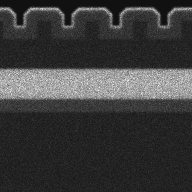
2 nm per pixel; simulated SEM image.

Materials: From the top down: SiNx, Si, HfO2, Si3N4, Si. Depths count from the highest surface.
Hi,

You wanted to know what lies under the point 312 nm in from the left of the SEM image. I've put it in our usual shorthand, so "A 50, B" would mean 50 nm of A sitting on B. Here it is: empty 6, SiNx 56, Si 60, HfO2 60, Si3N4 26, Si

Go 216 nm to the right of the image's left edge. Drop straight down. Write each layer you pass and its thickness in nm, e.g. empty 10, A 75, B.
empty 6, SiNx 56, Si 60, HfO2 60, Si3N4 26, Si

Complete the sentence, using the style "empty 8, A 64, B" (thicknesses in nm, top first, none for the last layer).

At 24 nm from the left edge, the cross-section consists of empty 6, SiNx 56, Si 60, HfO2 60, Si3N4 26, Si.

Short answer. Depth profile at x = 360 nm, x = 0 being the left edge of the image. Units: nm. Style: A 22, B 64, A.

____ SiNx 62, Si 60, HfO2 60, Si3N4 26, Si